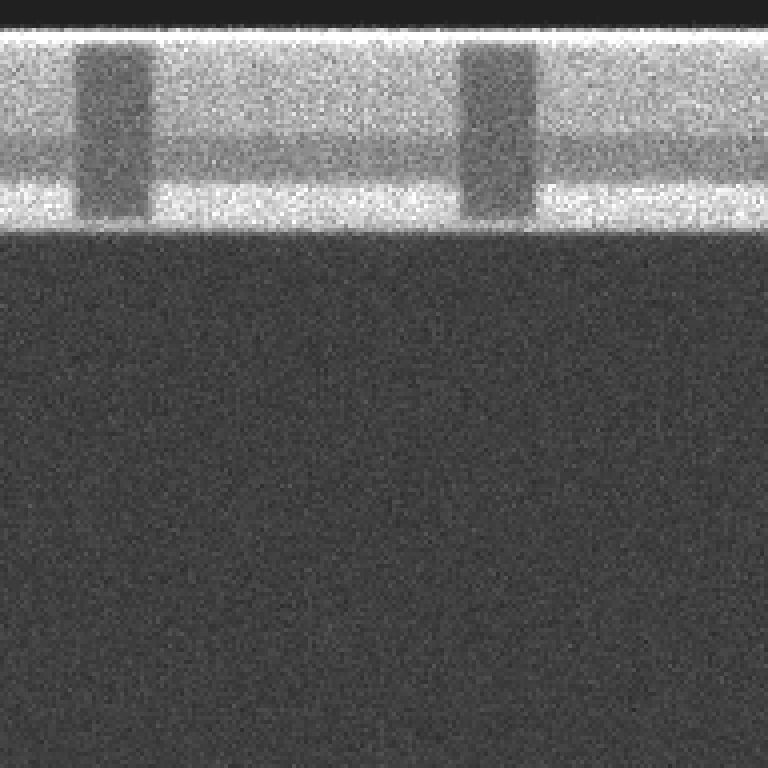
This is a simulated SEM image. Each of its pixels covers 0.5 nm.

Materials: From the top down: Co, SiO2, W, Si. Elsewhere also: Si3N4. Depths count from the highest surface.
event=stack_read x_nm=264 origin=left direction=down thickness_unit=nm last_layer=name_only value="Si3N4 94, W 6, Si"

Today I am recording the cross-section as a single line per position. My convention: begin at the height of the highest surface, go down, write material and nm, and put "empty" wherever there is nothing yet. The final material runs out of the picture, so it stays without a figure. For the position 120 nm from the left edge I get Co 52, SiO2 24, W 24, Si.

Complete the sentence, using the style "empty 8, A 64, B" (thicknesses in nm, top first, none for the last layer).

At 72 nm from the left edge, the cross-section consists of Si3N4 94, W 6, Si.